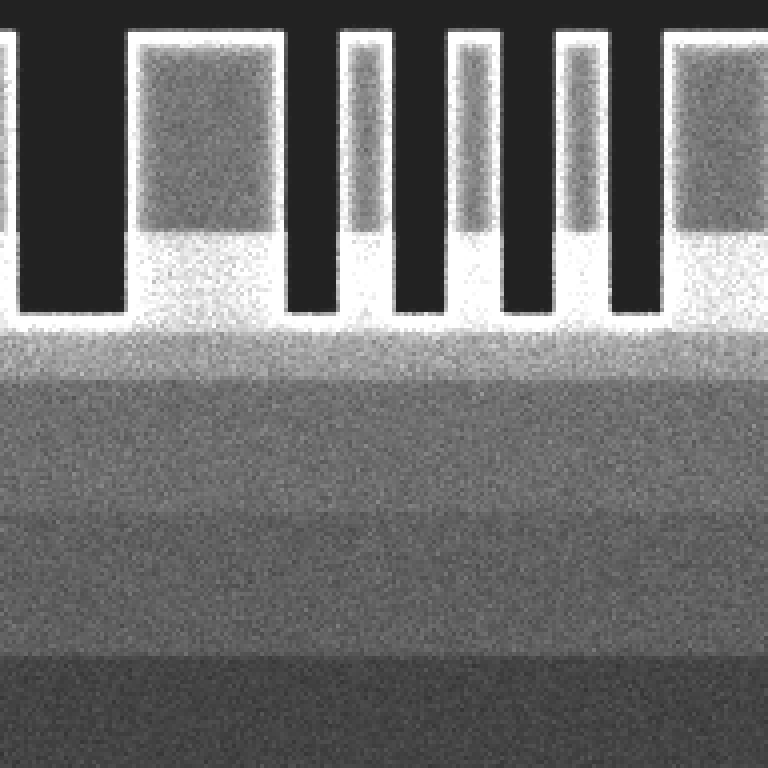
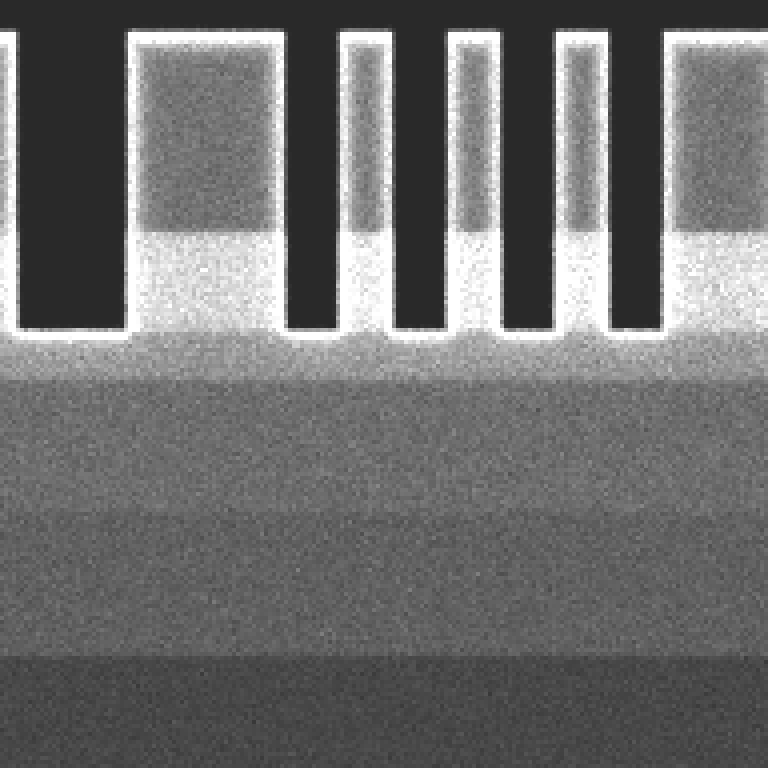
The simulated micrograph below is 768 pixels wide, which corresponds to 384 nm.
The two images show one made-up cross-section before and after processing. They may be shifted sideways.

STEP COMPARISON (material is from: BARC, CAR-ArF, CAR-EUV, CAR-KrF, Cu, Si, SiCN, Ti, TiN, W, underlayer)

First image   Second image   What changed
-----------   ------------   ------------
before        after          W, removed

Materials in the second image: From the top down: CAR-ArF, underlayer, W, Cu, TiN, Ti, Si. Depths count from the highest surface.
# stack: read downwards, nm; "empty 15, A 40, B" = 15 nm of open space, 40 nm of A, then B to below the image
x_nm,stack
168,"empty 150, Cu 24, TiN 66, Ti 72, Si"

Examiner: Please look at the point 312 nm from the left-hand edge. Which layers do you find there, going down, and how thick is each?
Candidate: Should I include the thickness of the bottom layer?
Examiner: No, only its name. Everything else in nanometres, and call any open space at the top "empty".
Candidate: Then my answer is empty 150, Cu 24, TiN 66, Ti 72, Si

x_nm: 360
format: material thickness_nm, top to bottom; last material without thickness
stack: CAR-ArF 44, underlayer 56, W 50, Cu 24, TiN 66, Ti 72, Si